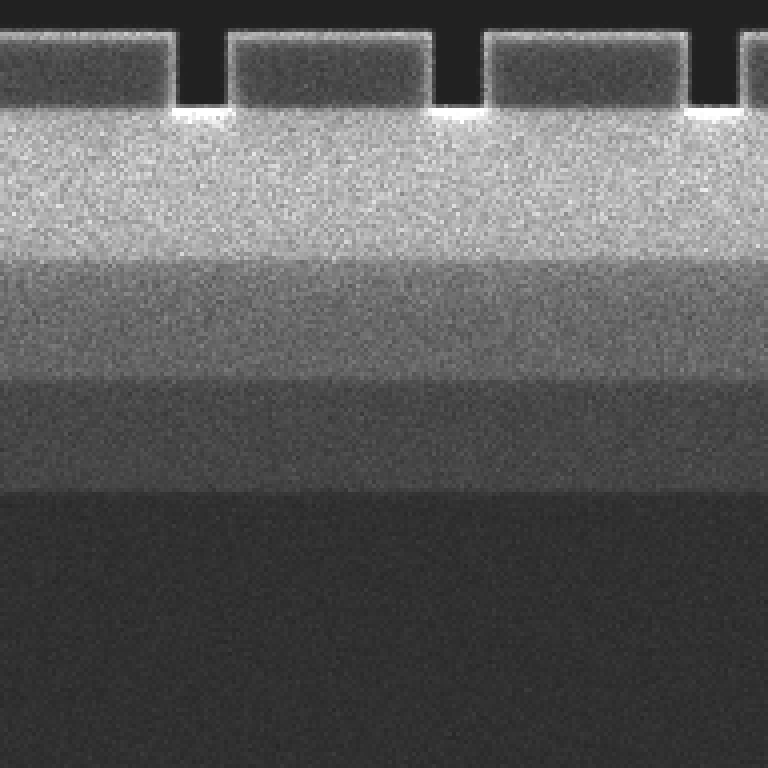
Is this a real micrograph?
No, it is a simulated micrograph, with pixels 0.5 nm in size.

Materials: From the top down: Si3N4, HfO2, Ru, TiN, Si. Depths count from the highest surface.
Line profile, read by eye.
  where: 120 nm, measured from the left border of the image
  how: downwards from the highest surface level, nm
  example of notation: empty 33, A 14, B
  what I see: Si3N4 38, HfO2 76, Ru 60, TiN 56, Si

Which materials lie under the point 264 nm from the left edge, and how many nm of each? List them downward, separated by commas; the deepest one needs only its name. Si3N4 38, HfO2 76, Ru 60, TiN 56, Si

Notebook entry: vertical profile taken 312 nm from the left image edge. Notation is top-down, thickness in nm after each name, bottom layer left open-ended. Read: Si3N4 38, HfO2 76, Ru 60, TiN 56, Si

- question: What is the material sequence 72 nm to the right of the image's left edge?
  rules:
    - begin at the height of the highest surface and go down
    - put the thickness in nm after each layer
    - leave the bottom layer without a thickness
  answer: Si3N4 38, HfO2 76, Ru 60, TiN 56, Si